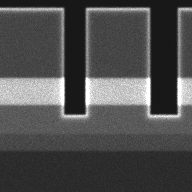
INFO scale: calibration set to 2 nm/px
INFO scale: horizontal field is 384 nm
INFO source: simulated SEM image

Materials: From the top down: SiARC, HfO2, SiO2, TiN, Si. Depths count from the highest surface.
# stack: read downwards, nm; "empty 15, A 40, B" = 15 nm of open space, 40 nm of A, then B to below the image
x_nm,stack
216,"SiARC 140, HfO2 54, SiO2 58, TiN 34, Si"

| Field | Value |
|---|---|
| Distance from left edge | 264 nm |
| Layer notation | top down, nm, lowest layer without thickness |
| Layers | SiARC 140, HfO2 54, SiO2 58, TiN 34, Si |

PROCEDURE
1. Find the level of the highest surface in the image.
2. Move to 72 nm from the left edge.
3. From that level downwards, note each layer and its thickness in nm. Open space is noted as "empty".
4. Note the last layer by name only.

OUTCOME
SiARC 140, HfO2 54, SiO2 58, TiN 34, Si